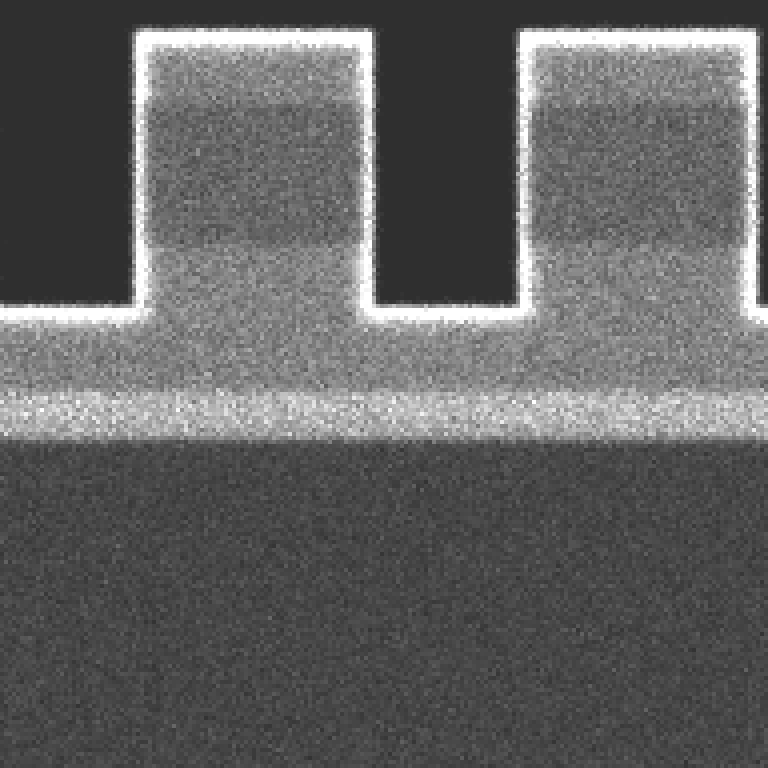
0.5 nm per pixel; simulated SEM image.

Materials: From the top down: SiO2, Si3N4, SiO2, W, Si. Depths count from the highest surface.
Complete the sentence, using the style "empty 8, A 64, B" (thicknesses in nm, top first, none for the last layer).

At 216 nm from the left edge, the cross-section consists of empty 138, SiO2 42, W 24, Si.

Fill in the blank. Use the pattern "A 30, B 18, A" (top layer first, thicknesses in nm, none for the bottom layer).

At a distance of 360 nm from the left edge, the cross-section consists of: SiO2 36, Si3N4 70, SiO2 74, W 24, Si